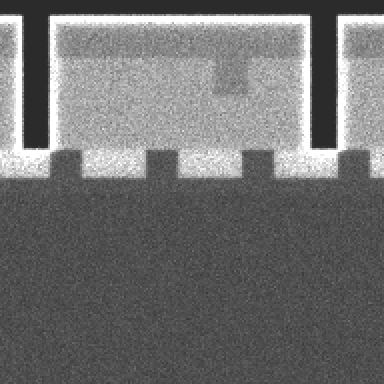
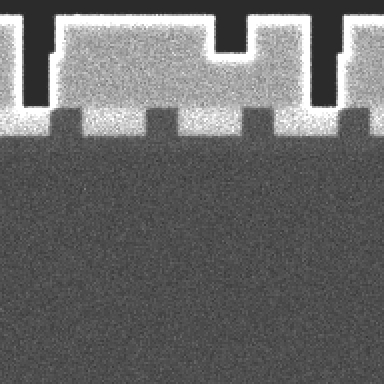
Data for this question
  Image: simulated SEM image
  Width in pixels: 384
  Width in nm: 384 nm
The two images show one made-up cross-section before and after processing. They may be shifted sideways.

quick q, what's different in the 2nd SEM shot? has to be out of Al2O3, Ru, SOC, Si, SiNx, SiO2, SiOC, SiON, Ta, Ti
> SOC removed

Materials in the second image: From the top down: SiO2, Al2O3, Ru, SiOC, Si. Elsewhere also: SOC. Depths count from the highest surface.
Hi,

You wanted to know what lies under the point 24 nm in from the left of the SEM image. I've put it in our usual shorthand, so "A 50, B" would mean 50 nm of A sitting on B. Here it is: empty 92, Ru 28, SiOC 16, Si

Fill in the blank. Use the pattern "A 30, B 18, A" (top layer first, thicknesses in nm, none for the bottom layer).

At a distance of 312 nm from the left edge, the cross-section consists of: empty 92, Ru 28, SiOC 16, Si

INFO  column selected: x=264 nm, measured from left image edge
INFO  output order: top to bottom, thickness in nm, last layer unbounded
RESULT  SiO2 84, Al2O3 8, SiOC 44, Si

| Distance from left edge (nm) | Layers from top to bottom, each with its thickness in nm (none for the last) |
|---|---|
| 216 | empty 38, SiO2 46, Al2O3 8, Ru 28, SiOC 16, Si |